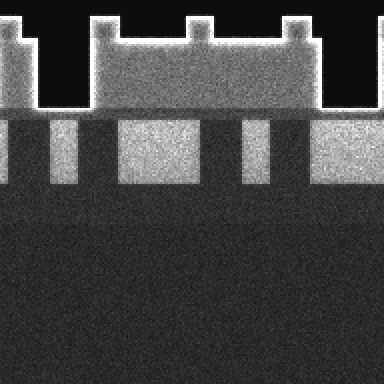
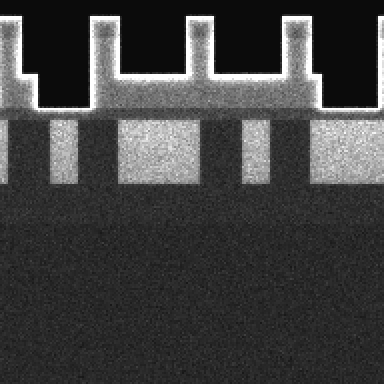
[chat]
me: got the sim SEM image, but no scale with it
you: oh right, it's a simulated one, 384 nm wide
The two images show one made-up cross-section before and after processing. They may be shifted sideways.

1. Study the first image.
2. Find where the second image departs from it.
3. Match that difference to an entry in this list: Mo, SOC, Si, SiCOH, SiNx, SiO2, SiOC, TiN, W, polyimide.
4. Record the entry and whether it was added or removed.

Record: SiO2 / removed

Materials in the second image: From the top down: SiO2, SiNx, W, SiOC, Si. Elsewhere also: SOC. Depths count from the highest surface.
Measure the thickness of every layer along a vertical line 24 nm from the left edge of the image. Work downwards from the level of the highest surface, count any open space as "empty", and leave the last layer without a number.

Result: empty 58, SiO2 34, SiNx 12, SiOC 104, Si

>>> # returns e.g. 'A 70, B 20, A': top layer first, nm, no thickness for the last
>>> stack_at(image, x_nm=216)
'empty 58, SiO2 34, SiNx 12, SiOC 104, Si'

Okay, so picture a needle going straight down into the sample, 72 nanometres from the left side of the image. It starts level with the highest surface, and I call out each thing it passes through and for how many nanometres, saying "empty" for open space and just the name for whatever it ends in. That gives empty 92, SiNx 12, W 64, SiOC 40, Si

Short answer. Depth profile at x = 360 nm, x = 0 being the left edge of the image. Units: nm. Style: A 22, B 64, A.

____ empty 92, SiNx 12, W 64, SiOC 40, Si